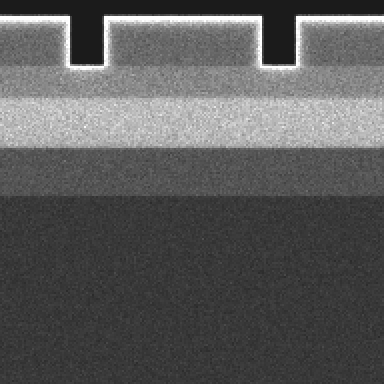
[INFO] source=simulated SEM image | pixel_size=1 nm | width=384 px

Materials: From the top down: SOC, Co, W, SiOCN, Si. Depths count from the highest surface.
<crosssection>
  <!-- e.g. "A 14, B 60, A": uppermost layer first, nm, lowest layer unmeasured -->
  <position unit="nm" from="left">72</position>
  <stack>empty 50, Co 32, W 50, SiOCN 48, Si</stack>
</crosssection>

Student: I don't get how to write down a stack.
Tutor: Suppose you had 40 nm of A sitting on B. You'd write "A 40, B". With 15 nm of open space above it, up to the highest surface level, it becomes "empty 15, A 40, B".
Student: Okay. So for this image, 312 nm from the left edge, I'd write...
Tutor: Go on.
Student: SOC 50, Co 32, W 50, SiOCN 48, Si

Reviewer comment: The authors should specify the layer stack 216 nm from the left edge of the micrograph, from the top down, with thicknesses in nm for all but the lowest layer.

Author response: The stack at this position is SOC 50, Co 32, W 50, SiOCN 48, Si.